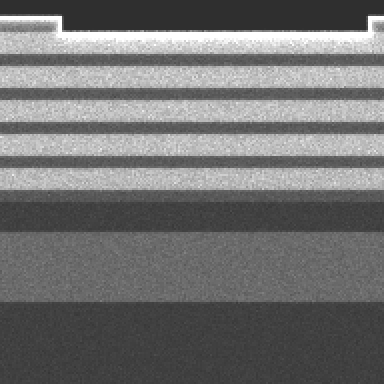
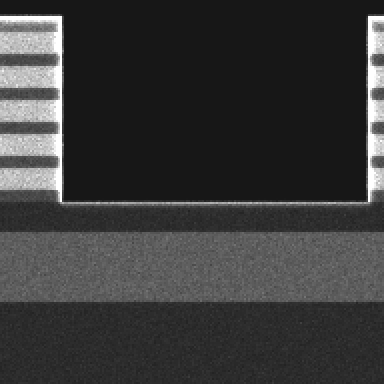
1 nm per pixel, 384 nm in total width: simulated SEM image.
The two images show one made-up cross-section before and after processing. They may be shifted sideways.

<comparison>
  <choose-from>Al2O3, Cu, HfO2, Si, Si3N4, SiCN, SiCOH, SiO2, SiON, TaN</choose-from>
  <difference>HfO2 and Si3N4 removed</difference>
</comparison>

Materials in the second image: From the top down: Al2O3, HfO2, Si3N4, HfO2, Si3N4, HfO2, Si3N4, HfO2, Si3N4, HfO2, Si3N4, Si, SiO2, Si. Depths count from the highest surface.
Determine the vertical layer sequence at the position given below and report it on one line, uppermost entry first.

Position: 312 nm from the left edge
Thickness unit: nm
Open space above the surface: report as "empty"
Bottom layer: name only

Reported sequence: empty 186, Si 30, SiO2 70, Si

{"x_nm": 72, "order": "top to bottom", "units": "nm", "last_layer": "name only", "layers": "empty 186, Si 30, SiO2 70, Si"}